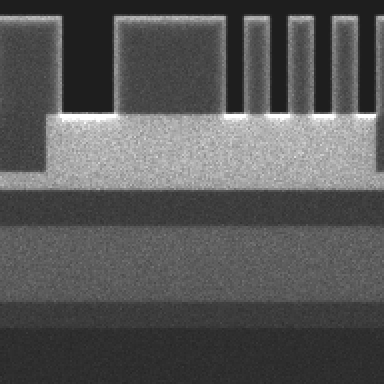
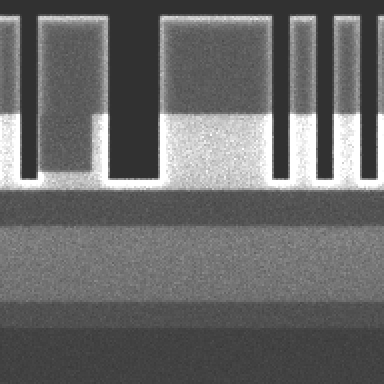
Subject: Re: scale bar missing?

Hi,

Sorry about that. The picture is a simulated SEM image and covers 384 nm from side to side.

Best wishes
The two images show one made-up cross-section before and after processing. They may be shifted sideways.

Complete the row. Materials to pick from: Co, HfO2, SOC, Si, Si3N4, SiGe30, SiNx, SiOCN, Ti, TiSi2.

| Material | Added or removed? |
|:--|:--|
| HfO2 | removed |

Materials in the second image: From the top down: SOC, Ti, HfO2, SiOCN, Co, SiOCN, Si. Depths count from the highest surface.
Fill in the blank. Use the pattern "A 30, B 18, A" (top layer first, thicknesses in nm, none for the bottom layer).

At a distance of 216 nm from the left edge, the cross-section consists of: SOC 98, HfO2 76, SiOCN 36, Co 76, SiOCN 26, Si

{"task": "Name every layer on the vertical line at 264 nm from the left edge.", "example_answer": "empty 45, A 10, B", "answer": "SOC 98, HfO2 76, SiOCN 36, Co 76, SiOCN 26, Si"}